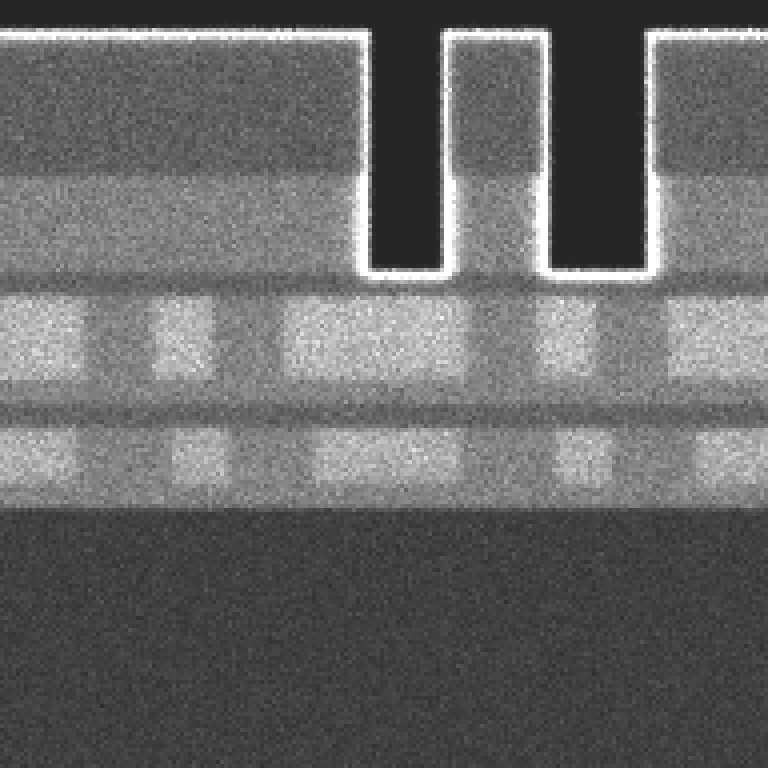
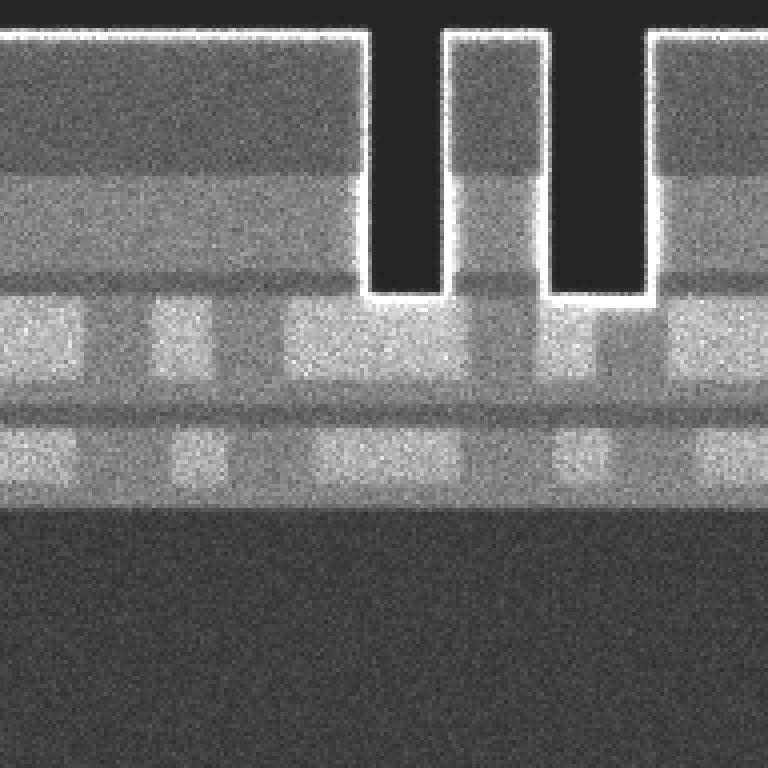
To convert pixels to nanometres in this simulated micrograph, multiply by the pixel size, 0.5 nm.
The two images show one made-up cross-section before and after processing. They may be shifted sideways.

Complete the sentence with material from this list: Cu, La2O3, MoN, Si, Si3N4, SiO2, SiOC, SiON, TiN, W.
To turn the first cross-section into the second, Si3N4 must be removed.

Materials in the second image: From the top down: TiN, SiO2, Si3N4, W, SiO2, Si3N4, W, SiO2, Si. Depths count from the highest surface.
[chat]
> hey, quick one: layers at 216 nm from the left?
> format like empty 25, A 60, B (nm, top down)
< empty 132, W 42, SiO2 12, Si3N4 12, W 28, SiO2 12, Si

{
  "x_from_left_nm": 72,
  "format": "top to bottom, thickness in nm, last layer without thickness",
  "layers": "TiN 72, SiO2 48, Si3N4 12, SiO2 54, Si3N4 12, SiO2 40, Si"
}